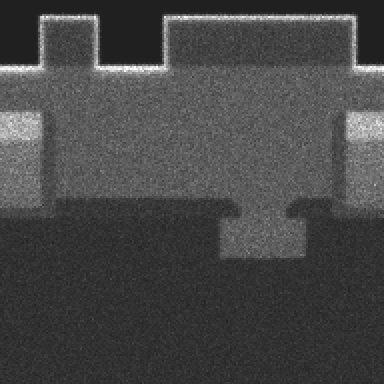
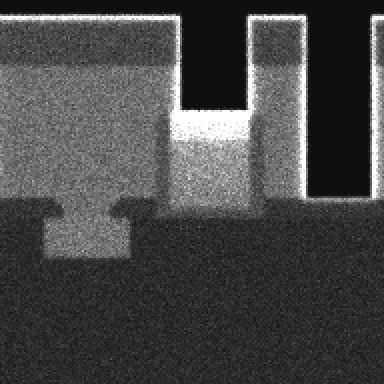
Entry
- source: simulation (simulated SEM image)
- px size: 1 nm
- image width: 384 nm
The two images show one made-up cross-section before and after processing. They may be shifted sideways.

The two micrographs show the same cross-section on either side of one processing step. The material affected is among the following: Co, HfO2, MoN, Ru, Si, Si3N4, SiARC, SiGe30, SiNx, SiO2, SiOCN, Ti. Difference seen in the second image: SiO2 removed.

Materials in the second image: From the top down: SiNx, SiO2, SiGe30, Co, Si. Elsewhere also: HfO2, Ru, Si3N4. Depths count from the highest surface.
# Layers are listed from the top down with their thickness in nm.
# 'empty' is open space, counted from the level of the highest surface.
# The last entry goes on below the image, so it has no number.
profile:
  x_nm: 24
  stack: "SiNx 50, SiO2 132, SiGe30 20, Si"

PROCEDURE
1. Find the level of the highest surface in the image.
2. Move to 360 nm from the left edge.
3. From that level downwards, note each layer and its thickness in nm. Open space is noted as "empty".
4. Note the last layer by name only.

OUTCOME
empty 182, SiGe30 20, Si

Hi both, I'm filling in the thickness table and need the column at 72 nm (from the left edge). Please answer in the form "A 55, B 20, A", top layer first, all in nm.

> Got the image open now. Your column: SiNx 50, SiO2 152, Co 40, Si